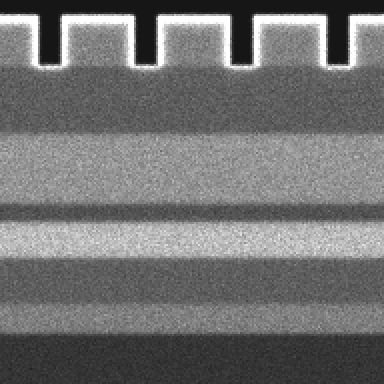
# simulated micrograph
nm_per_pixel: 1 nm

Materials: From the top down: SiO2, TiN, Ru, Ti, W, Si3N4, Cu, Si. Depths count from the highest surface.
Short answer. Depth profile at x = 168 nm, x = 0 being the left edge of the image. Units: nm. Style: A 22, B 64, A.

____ SiO2 50, TiN 68, Ru 70, Ti 18, W 36, Si3N4 46, Cu 30, Si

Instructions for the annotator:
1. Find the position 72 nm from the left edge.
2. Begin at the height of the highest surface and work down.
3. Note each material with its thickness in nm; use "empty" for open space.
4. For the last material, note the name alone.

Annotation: SiO2 50, TiN 68, Ru 70, Ti 18, W 36, Si3N4 46, Cu 30, Si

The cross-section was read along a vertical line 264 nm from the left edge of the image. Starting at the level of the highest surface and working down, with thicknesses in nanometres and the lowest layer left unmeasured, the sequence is SiO2 50, TiN 68, Ru 70, Ti 18, W 36, Si3N4 46, Cu 30, Si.